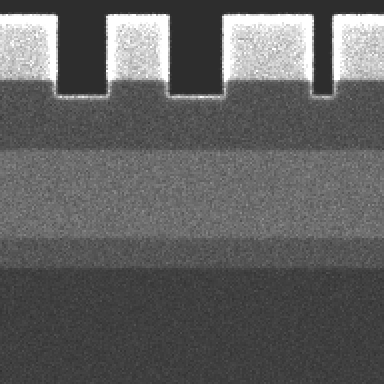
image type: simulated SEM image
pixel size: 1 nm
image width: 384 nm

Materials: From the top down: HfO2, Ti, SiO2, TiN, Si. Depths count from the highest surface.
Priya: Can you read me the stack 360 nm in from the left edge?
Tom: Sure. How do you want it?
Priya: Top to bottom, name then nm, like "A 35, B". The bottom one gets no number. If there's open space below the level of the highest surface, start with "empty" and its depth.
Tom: HfO2 64, Ti 70, SiO2 88, TiN 30, Si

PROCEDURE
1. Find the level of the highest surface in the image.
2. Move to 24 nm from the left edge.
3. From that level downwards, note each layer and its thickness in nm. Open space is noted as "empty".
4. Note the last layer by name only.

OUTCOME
HfO2 64, Ti 70, SiO2 88, TiN 30, Si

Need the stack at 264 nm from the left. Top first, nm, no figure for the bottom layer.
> HfO2 64, Ti 70, SiO2 88, TiN 30, Si